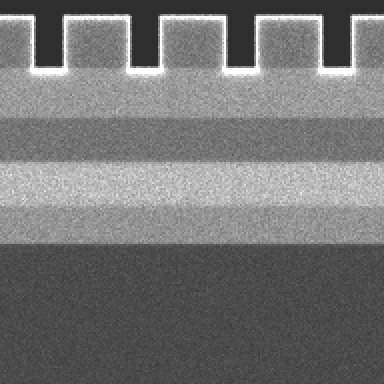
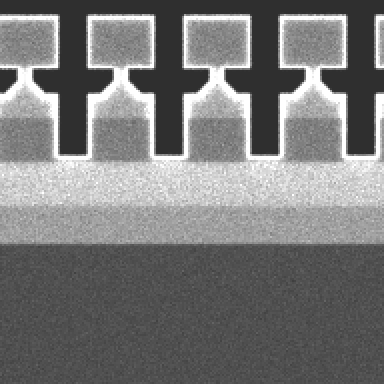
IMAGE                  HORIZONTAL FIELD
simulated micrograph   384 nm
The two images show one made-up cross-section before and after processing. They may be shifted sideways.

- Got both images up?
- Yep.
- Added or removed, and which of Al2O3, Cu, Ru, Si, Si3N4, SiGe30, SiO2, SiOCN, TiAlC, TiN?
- removed, Al2O3 and Si3N4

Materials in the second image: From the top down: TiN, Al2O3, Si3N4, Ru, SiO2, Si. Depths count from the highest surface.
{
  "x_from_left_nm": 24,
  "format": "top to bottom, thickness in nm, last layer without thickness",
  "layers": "TiN 52, Al2O3 50, Si3N4 44, Ru 44, SiO2 38, Si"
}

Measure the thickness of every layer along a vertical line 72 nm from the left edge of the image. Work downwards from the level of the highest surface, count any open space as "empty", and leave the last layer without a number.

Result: empty 140, Si3N4 6, Ru 44, SiO2 38, Si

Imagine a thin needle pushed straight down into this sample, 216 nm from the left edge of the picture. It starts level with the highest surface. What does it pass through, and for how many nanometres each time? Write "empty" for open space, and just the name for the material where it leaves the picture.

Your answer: TiN 52, Al2O3 50, Si3N4 44, Ru 44, SiO2 38, Si